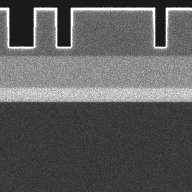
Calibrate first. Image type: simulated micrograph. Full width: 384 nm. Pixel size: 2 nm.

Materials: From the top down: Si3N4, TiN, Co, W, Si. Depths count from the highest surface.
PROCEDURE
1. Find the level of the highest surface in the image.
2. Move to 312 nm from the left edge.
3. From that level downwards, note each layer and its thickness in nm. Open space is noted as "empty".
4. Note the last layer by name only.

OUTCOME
empty 78, TiN 18, Co 64, W 28, Si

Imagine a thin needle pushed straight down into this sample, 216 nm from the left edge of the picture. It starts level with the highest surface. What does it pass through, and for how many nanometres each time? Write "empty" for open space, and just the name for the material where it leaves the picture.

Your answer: Si3N4 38, TiN 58, Co 64, W 28, Si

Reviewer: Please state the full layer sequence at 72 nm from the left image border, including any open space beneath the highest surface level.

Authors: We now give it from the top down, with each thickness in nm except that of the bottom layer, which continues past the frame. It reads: Si3N4 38, TiN 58, Co 64, W 28, Si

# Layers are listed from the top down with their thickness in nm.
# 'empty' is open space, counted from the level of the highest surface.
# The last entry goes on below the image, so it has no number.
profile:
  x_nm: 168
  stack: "Si3N4 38, TiN 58, Co 64, W 28, Si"